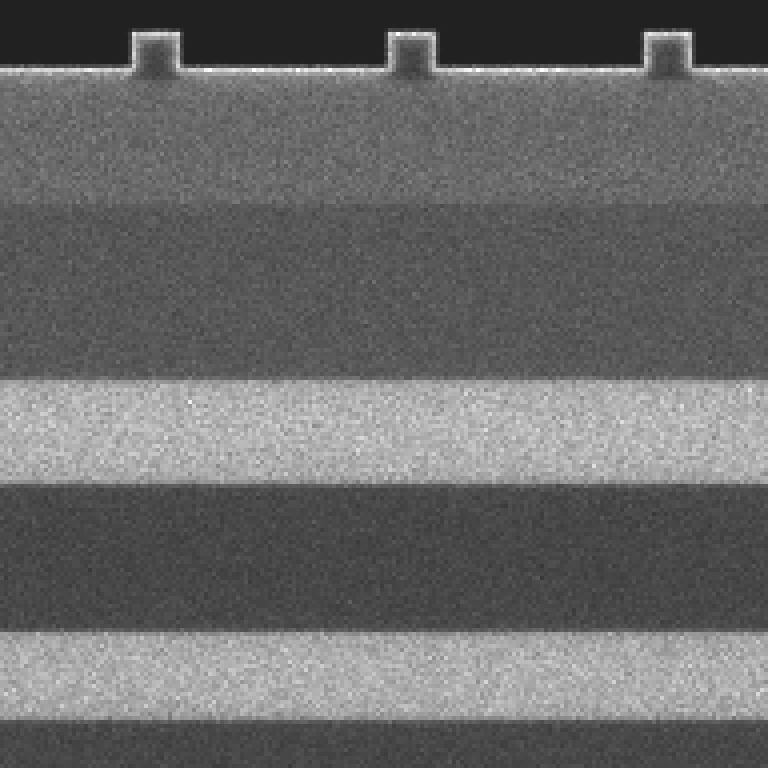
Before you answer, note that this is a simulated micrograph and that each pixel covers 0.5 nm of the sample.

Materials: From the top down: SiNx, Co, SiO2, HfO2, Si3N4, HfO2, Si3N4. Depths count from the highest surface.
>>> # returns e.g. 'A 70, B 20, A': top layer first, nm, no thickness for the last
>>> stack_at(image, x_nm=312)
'empty 18, Co 68, SiO2 88, HfO2 52, Si3N4 74, HfO2 44, Si3N4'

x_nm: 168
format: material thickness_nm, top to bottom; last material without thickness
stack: empty 18, Co 68, SiO2 88, HfO2 52, Si3N4 74, HfO2 44, Si3N4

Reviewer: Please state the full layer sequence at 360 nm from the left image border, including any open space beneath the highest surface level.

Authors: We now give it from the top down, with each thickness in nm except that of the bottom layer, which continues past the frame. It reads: empty 18, Co 68, SiO2 88, HfO2 52, Si3N4 74, HfO2 44, Si3N4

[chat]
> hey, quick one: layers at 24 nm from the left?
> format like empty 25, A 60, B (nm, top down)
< empty 18, Co 68, SiO2 88, HfO2 52, Si3N4 74, HfO2 44, Si3N4